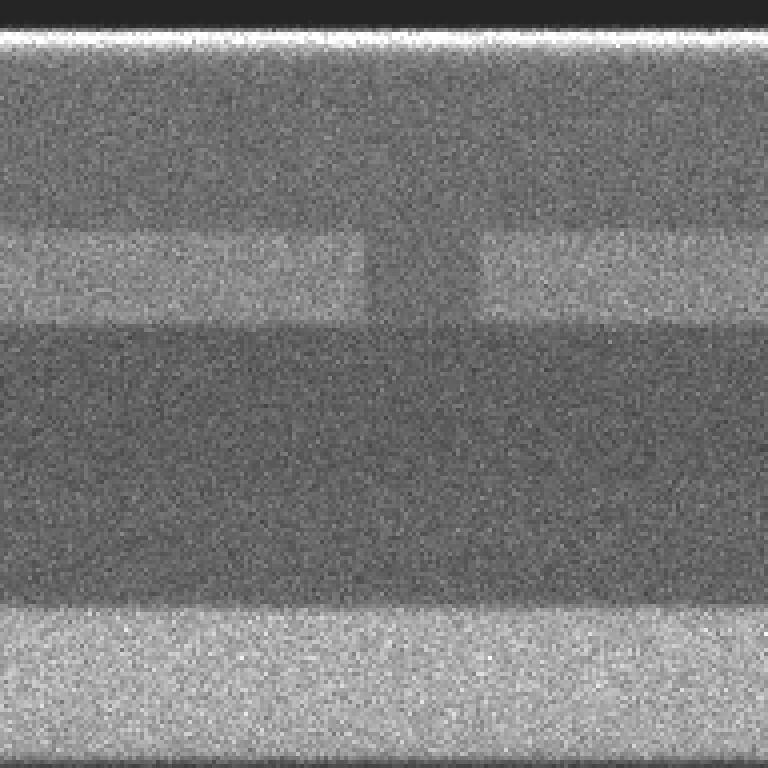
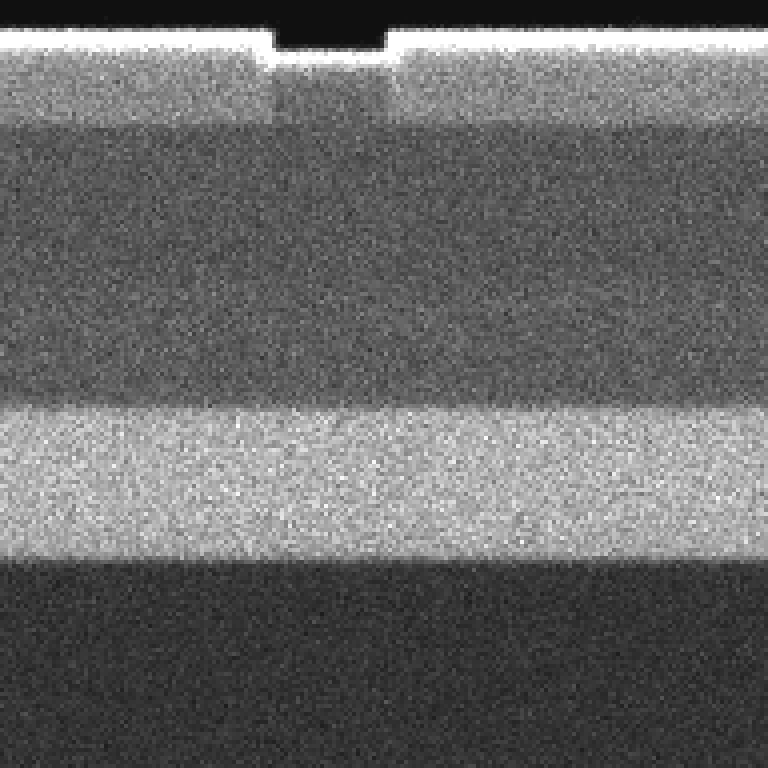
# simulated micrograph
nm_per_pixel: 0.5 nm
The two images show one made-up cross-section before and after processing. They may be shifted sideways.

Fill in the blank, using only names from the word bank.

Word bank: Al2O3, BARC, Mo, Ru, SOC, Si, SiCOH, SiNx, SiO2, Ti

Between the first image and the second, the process removed SOC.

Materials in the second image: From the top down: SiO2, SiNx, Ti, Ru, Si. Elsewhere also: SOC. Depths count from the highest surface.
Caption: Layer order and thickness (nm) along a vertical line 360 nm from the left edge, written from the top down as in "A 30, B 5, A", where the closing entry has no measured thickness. SiO2 46, SiNx 78, Ti 64, Ru 76, Si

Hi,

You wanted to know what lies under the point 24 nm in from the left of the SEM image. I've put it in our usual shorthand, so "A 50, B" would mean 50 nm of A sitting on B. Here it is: SiO2 46, SiNx 78, Ti 64, Ru 76, Si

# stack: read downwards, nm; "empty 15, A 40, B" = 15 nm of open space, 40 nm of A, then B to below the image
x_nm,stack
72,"SiO2 46, SiNx 78, Ti 64, Ru 76, Si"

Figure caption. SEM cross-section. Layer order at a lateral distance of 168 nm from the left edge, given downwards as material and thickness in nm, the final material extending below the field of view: empty 10, SOC 36, SiNx 78, Ti 64, Ru 76, Si